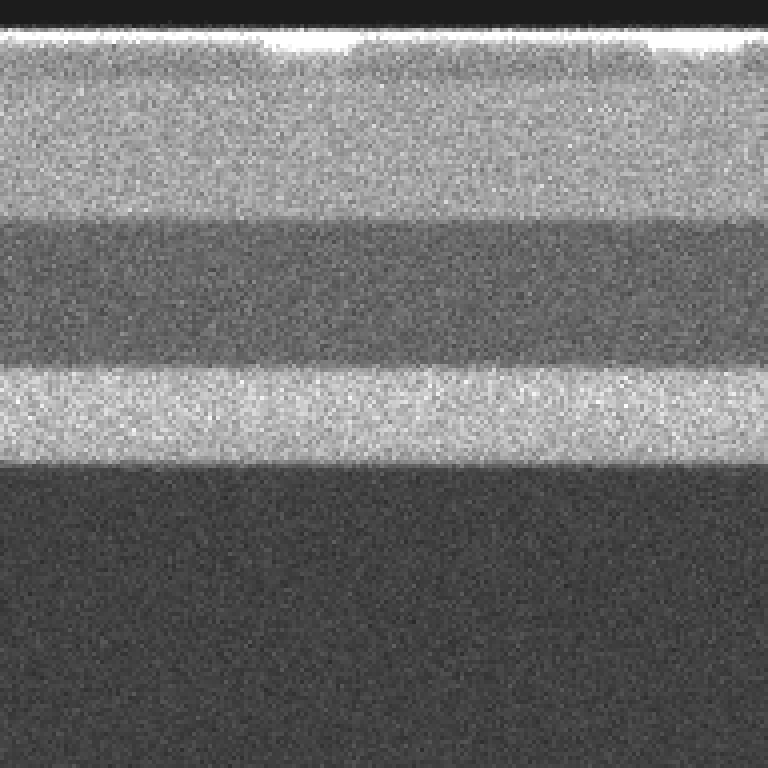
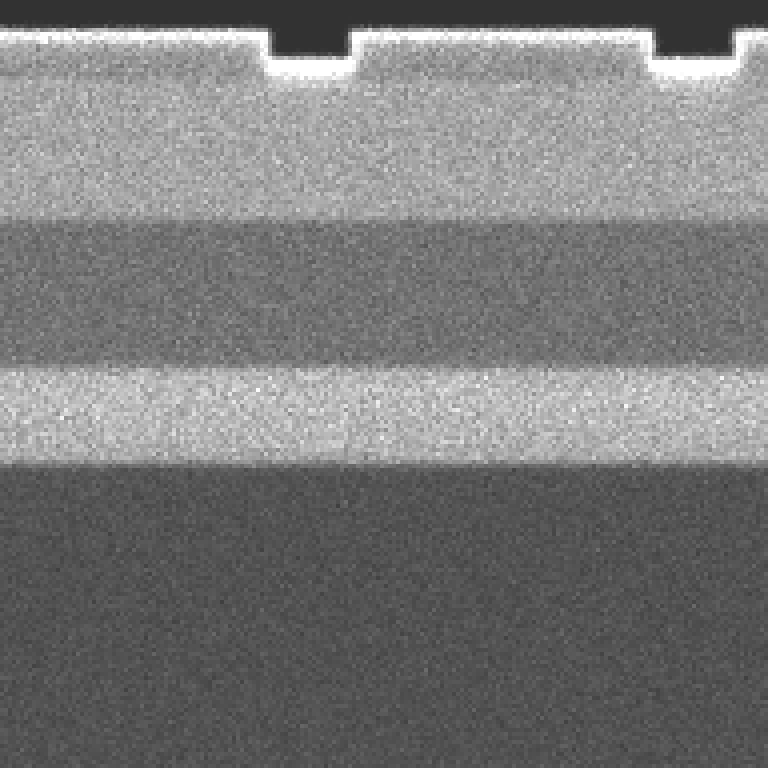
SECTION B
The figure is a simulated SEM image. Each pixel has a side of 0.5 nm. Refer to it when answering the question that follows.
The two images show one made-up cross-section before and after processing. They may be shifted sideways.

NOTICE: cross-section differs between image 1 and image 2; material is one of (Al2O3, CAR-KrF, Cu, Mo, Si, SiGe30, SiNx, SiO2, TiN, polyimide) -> removed: SiO2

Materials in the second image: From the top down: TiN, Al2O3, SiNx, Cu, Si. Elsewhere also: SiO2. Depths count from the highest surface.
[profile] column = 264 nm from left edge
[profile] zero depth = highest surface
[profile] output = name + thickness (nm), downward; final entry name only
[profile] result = TiN 24, Al2O3 70, SiNx 74, Cu 48, Si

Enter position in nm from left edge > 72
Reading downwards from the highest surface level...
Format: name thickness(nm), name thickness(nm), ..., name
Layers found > TiN 24, Al2O3 70, SiNx 74, Cu 48, Si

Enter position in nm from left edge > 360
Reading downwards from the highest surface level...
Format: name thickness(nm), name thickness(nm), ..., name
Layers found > empty 14, SiO2 10, Al2O3 70, SiNx 74, Cu 48, Si